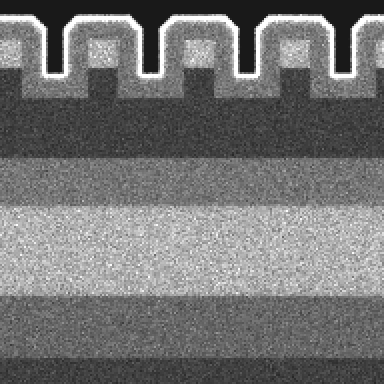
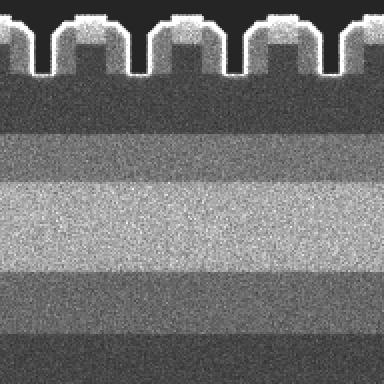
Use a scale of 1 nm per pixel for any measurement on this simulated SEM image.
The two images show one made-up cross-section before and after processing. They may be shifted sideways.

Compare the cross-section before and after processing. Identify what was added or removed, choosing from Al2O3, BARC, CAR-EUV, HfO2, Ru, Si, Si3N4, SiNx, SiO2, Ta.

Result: Si3N4 removed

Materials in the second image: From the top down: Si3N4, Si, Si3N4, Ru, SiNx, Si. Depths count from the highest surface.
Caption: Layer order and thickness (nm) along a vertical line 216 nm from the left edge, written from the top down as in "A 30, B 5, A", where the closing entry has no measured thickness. empty 10, Si3N4 48, Si 60, Si3N4 48, Ru 90, SiNx 62, Si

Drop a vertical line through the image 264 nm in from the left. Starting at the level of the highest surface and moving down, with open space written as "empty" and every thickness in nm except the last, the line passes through empty 6, Si3N4 52, Si 60, Si3N4 48, Ru 90, SiNx 62, Si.